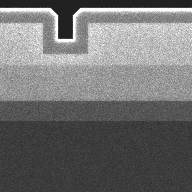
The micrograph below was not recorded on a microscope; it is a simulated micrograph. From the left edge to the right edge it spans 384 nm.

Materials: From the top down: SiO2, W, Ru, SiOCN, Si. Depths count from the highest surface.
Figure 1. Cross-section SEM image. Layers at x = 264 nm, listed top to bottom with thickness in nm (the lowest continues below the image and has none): SiO2 30, W 84, Ru 72, SiOCN 40, Si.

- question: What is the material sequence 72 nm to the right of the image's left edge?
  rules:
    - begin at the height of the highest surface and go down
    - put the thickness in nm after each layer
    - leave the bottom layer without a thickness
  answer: SiO2 30, W 84, Ru 72, SiOCN 40, Si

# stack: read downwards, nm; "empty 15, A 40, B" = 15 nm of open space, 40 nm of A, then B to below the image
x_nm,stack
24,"SiO2 30, W 84, Ru 72, SiOCN 40, Si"